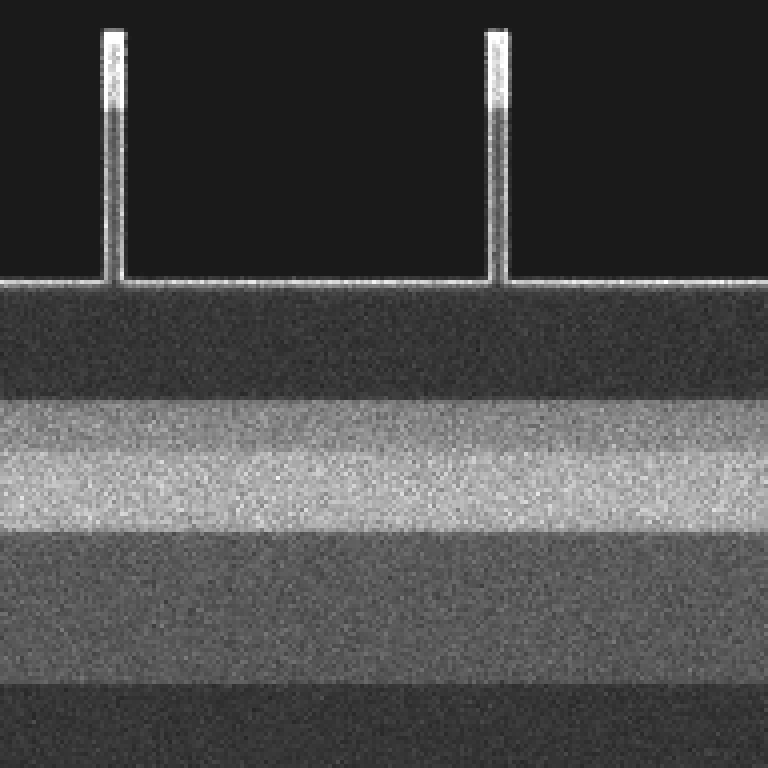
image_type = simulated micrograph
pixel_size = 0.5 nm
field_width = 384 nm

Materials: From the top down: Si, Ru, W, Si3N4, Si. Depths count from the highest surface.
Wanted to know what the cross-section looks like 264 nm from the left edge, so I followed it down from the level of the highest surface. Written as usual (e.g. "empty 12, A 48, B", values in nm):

empty 124, Si 60, Ru 26, W 40, Si3N4 76, Si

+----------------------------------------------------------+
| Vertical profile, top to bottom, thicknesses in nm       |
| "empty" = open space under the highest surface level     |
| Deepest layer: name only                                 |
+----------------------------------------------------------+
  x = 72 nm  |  empty 124, Si 60, Ru 26, W 40, Si3N4 76, Si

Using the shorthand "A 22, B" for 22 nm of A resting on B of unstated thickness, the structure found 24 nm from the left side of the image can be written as empty 124, Si 60, Ru 26, W 40, Si3N4 76, Si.